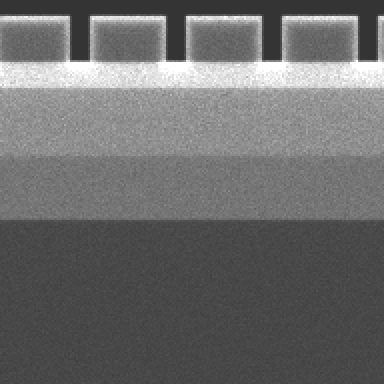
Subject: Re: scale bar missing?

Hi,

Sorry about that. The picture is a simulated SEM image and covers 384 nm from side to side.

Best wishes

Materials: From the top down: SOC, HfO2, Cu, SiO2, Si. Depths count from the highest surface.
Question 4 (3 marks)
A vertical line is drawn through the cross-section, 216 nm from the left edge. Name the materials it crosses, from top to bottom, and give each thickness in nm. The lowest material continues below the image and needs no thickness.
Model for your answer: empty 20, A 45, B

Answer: SOC 46, HfO2 26, Cu 68, SiO2 64, Si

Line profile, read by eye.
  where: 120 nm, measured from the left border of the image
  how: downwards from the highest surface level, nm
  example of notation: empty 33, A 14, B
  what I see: SOC 46, HfO2 26, Cu 68, SiO2 64, Si